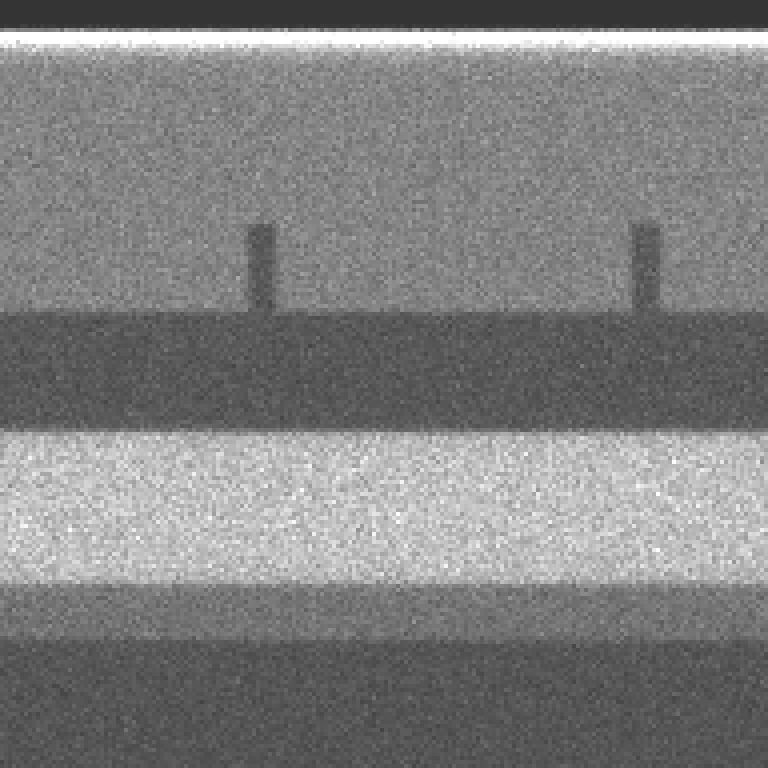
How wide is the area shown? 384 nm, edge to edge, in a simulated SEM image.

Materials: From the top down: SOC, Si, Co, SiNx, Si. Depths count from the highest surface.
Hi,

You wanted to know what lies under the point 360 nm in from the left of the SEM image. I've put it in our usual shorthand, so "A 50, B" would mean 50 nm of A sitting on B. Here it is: SOC 140, Si 60, Co 76, SiNx 28, Si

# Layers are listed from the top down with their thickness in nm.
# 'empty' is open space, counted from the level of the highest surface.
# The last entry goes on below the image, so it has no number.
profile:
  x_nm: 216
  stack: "SOC 140, Si 60, Co 76, SiNx 28, Si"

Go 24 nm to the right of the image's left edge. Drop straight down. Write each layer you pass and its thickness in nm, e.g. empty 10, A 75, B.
SOC 140, Si 60, Co 76, SiNx 28, Si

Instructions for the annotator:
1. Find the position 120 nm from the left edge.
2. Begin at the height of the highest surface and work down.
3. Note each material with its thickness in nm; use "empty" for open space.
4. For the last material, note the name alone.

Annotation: SOC 140, Si 60, Co 76, SiNx 28, Si